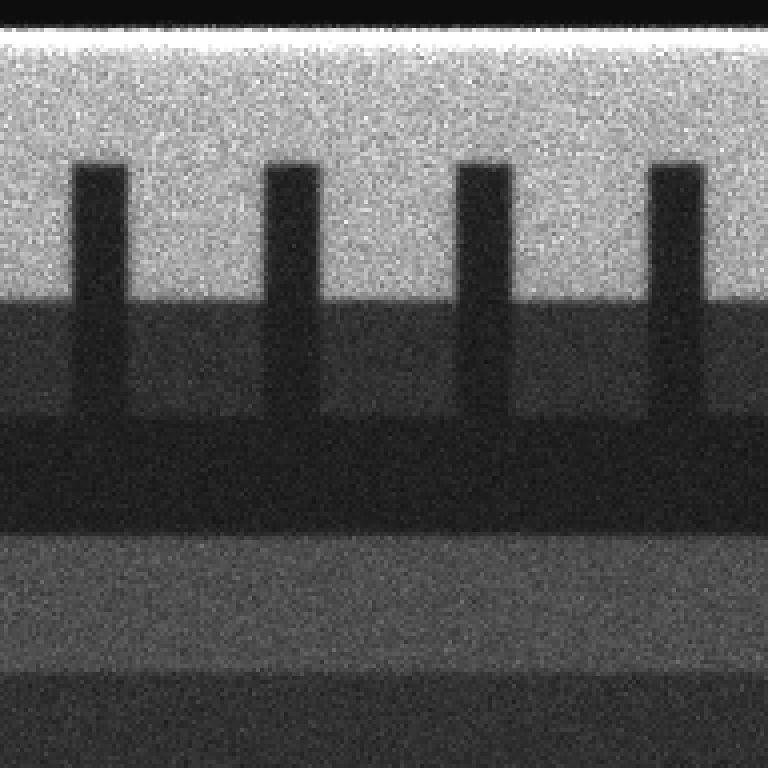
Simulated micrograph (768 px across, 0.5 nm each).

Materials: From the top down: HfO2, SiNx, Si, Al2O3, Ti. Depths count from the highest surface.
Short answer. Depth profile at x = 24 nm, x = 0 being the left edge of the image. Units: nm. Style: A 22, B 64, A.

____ HfO2 134, SiNx 58, Si 60, Al2O3 68, Ti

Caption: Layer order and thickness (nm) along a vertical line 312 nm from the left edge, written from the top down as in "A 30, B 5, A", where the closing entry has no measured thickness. HfO2 134, SiNx 58, Si 60, Al2O3 68, Ti